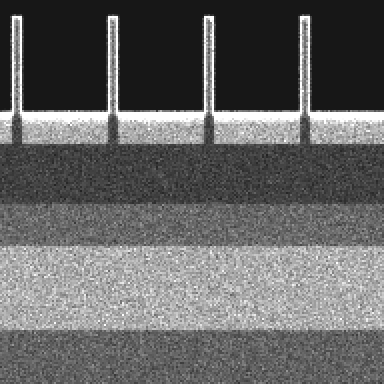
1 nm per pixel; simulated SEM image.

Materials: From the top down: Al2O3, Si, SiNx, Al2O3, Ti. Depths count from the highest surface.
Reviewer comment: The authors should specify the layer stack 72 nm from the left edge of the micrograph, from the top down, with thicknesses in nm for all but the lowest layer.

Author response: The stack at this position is empty 96, Al2O3 32, Si 60, SiNx 42, Al2O3 84, Ti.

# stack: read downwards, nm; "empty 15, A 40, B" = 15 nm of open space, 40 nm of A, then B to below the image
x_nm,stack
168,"empty 96, Al2O3 32, Si 60, SiNx 42, Al2O3 84, Ti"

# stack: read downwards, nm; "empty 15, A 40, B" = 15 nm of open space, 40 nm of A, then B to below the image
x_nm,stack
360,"empty 96, Al2O3 32, Si 60, SiNx 42, Al2O3 84, Ti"